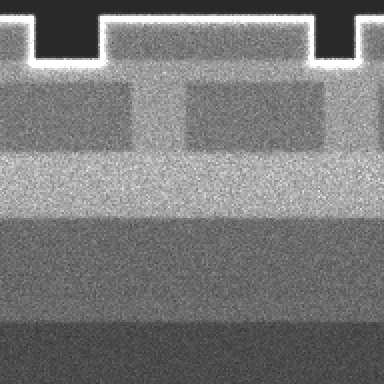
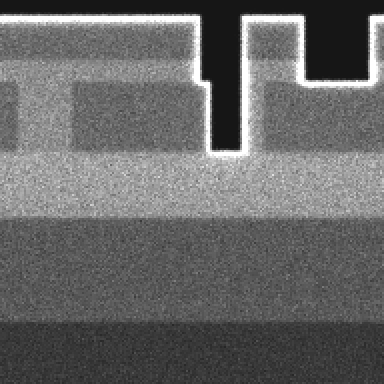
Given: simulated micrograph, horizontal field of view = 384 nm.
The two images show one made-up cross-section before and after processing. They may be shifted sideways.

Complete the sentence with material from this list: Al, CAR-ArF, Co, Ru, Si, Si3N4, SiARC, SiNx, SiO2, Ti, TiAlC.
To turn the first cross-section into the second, SiO2 must be removed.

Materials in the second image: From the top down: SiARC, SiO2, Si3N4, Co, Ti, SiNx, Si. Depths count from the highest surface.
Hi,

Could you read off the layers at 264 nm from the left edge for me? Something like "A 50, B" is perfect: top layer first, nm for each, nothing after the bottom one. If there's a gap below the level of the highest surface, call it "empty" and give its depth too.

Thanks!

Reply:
SiARC 44, SiO2 22, Si3N4 70, Co 66, Ti 80, SiNx 24, Si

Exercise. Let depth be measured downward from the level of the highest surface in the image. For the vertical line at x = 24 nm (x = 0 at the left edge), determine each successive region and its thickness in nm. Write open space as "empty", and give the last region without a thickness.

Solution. SiARC 44, SiO2 92, Co 66, Ti 80, SiNx 24, Si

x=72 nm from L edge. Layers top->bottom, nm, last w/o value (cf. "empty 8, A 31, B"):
SiARC 44, SiO2 22, Si3N4 70, Co 66, Ti 80, SiNx 24, Si